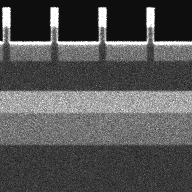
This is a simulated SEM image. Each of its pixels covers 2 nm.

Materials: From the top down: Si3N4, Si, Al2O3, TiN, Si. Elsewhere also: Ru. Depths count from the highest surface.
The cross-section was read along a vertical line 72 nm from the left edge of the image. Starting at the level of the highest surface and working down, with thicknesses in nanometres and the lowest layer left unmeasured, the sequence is empty 68, Si3N4 38, Si 60, Al2O3 44, TiN 64, Si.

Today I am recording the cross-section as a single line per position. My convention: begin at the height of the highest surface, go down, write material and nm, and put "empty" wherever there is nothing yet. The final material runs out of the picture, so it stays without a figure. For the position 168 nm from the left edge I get empty 68, Si3N4 38, Si 60, Al2O3 44, TiN 64, Si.